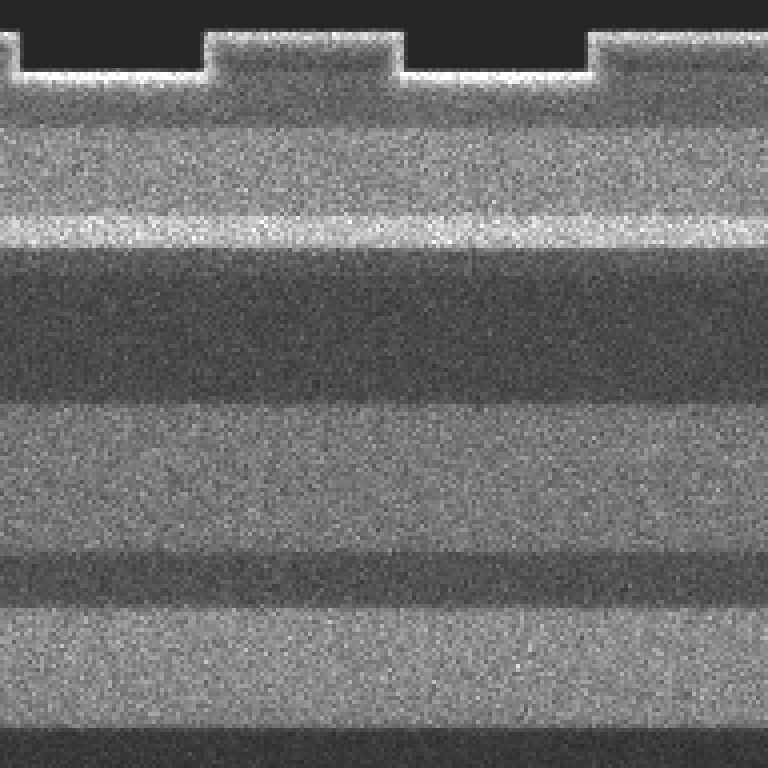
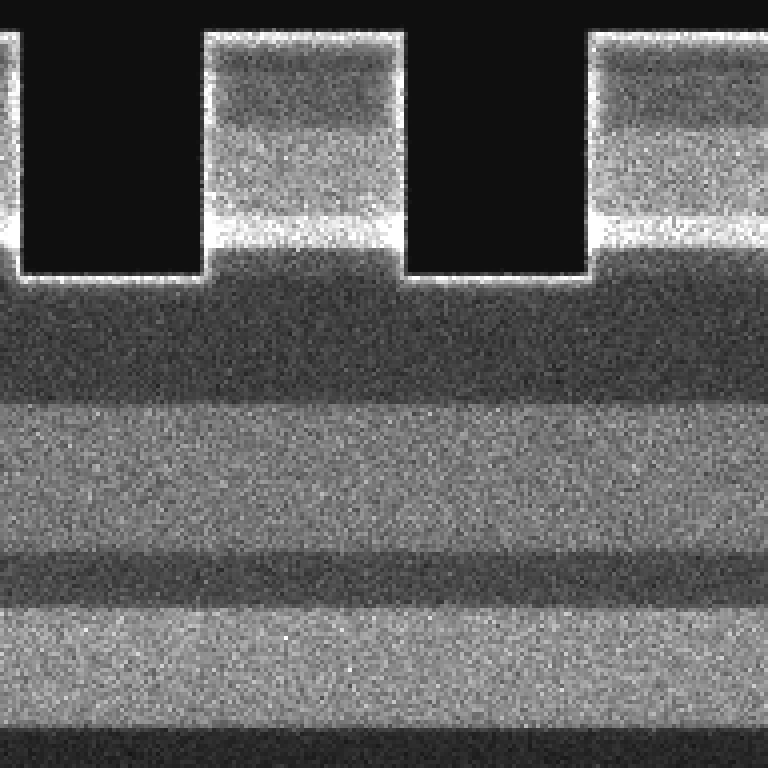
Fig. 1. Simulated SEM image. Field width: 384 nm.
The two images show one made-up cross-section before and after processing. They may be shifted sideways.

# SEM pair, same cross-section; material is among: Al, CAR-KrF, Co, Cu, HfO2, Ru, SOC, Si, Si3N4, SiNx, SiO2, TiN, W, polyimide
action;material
removed;HfO2 and Ru and SiO2 and TiN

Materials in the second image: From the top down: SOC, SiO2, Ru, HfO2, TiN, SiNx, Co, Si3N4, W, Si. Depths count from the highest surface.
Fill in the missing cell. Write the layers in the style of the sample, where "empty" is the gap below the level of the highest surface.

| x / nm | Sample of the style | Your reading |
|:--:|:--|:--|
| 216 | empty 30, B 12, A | empty 122, SiNx 64, Co 74, Si3N4 28, W 60, Si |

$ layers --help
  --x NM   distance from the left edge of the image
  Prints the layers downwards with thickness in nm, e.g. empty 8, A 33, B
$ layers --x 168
SOC 20, SiO2 28, Ru 44, HfO2 16, TiN 14, SiNx 64, Co 74, Si3N4 28, W 60, Si